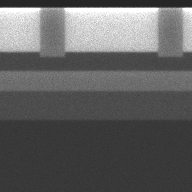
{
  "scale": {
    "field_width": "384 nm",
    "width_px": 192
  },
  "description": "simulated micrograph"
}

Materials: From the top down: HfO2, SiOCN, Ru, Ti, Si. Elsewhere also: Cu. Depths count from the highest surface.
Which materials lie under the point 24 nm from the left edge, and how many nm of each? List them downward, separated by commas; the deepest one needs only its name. HfO2 88, SiOCN 38, Ru 40, Ti 58, Si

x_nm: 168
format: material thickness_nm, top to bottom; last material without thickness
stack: HfO2 88, SiOCN 38, Ru 40, Ti 58, Si